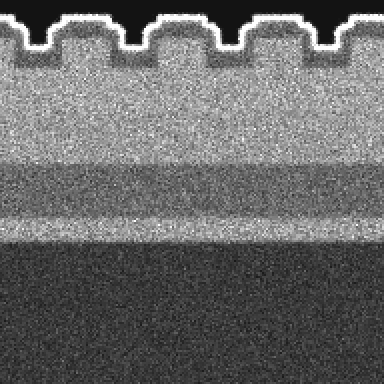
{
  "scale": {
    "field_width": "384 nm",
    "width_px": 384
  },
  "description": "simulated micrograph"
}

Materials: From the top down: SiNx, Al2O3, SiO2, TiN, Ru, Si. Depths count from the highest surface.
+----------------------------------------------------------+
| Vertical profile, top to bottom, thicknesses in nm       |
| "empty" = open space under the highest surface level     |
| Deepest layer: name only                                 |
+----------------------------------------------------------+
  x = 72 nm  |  SiNx 22, Al2O3 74, SiO2 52, TiN 54, Ru 24, Si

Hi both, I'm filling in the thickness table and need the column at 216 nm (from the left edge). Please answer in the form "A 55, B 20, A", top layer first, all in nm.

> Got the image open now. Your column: empty 12, SiNx 40, Al2O3 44, SiO2 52, TiN 54, Ru 24, Si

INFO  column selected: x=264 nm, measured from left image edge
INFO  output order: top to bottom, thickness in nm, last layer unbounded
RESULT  SiNx 22, Al2O3 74, SiO2 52, TiN 54, Ru 24, Si